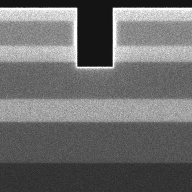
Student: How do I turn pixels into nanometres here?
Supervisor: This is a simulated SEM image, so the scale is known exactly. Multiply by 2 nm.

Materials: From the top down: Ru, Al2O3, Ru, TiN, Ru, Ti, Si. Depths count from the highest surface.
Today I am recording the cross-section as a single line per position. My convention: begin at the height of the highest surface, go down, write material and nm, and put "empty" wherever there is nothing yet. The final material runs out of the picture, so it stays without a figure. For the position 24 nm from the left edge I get Ru 26, Al2O3 50, Ru 32, TiN 74, Ru 46, Ti 82, Si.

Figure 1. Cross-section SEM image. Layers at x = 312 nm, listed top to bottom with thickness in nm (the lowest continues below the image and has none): Ru 26, Al2O3 50, Ru 32, TiN 74, Ru 46, Ti 82, Si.